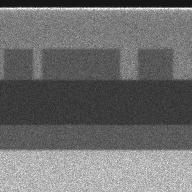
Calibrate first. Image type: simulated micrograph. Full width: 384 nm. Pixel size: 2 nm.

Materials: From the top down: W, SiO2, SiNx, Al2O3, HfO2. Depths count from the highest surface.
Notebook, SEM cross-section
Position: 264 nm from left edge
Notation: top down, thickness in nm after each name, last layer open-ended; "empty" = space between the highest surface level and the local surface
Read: W 144, SiNx 90, Al2O3 50, HfO2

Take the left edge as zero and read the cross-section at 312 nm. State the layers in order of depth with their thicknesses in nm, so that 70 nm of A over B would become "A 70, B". W 82, SiO2 62, SiNx 90, Al2O3 50, HfO2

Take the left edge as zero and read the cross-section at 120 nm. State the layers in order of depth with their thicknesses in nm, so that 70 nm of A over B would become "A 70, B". W 82, SiO2 62, SiNx 90, Al2O3 50, HfO2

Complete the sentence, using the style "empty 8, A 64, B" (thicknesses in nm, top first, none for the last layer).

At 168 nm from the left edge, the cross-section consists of W 82, SiO2 62, SiNx 90, Al2O3 50, HfO2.